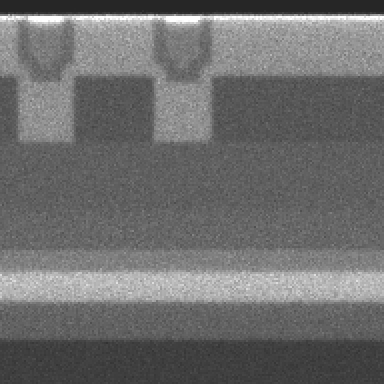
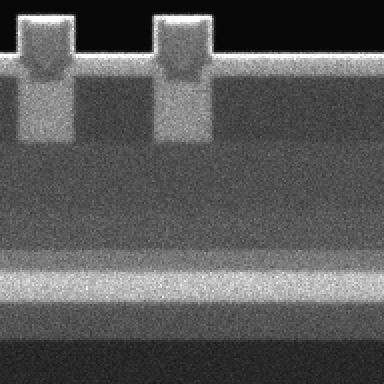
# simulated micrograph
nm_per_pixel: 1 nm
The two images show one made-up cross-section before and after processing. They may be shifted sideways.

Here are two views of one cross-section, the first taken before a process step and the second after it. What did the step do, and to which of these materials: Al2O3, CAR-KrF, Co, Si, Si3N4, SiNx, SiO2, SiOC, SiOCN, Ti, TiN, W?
It removed Co.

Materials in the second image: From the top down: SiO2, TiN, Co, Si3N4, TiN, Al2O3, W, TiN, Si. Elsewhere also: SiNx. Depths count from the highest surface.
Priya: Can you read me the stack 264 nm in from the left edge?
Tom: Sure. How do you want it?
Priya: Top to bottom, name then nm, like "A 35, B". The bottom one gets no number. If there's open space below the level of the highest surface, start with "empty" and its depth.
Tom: empty 38, Co 22, SiNx 66, Si3N4 68, TiN 40, Al2O3 22, W 30, TiN 38, Si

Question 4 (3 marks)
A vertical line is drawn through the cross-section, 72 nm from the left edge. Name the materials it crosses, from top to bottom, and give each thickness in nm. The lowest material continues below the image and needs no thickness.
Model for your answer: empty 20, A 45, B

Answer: TiN 48, Co 78, Si3N4 68, TiN 40, Al2O3 22, W 30, TiN 38, Si